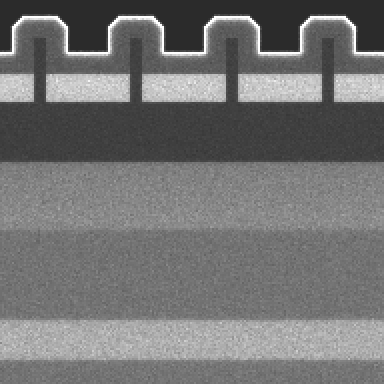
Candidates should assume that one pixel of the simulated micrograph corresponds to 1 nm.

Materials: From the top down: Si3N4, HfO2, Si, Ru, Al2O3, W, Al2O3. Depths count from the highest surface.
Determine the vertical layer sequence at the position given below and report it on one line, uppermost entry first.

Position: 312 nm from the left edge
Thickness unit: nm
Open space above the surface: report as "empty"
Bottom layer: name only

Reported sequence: Si3N4 58, HfO2 28, Si 60, Ru 68, Al2O3 90, W 40, Al2O3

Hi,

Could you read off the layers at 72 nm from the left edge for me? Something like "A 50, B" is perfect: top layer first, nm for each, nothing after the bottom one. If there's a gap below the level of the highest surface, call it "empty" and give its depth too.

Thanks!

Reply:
empty 36, Si3N4 22, HfO2 28, Si 60, Ru 68, Al2O3 90, W 40, Al2O3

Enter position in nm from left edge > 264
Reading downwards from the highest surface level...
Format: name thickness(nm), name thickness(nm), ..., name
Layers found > empty 36, Si3N4 22, HfO2 28, Si 60, Ru 68, Al2O3 90, W 40, Al2O3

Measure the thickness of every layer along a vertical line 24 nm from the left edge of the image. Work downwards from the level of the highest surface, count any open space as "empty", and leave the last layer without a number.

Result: Si3N4 58, HfO2 28, Si 60, Ru 68, Al2O3 90, W 40, Al2O3